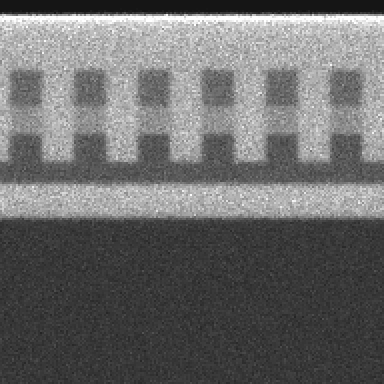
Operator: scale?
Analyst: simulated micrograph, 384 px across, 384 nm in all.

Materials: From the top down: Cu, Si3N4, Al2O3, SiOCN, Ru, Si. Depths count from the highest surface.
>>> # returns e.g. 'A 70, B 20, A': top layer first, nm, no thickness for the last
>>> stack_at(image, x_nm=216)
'Cu 54, Si3N4 36, Al2O3 28, SiOCN 50, Ru 34, Si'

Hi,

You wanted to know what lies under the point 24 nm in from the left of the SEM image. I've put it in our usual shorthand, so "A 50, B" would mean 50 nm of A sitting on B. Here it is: Cu 54, Si3N4 36, Al2O3 28, SiOCN 50, Ru 34, Si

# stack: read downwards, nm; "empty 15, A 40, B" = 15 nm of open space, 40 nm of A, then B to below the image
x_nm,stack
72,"Cu 146, SiOCN 22, Ru 34, Si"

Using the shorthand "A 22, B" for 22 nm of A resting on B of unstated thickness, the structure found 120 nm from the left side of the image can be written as Cu 146, SiOCN 22, Ru 34, Si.